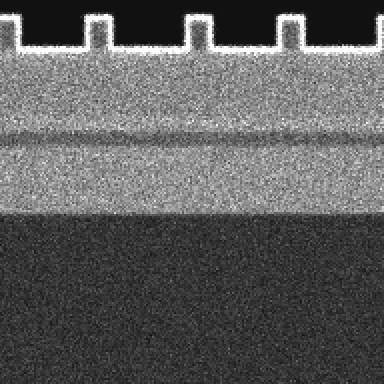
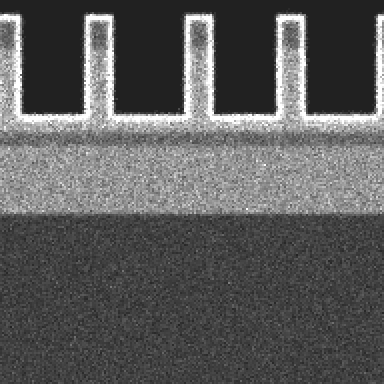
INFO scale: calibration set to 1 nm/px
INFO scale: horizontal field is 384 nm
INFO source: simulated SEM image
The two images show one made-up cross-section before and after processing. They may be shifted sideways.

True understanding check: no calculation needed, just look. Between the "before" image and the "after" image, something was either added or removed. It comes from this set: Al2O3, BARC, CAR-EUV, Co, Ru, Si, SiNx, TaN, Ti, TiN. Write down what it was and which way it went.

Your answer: Co (removed)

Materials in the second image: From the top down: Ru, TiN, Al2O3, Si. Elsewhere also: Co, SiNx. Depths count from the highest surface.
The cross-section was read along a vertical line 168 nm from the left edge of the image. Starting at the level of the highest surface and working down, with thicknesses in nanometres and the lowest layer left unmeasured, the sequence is empty 100, Ru 16, TiN 14, Al2O3 68, Si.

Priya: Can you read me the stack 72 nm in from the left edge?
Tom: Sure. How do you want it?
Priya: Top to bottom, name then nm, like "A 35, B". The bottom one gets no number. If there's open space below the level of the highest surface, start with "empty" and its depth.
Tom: empty 100, Ru 16, TiN 14, Al2O3 68, Si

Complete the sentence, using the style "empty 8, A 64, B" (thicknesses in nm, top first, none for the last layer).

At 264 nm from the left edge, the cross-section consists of empty 100, Ru 16, TiN 14, Al2O3 68, Si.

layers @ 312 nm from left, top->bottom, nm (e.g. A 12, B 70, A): empty 100, Ru 16, TiN 14, Al2O3 68, Si